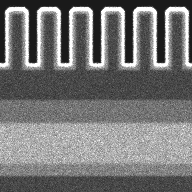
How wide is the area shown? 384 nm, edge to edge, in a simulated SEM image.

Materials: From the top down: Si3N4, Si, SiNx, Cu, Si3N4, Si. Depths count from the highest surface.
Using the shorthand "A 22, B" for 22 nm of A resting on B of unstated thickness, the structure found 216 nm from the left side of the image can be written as Si3N4 12, Si 172, SiNx 46, Cu 82, Si3N4 24, Si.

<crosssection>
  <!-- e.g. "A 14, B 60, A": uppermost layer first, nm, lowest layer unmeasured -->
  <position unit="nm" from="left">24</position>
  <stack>Si3N4 12, Si 172, SiNx 46, Cu 82, Si3N4 24, Si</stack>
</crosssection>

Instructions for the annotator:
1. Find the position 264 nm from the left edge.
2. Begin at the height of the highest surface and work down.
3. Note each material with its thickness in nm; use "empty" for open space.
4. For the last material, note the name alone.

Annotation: empty 112, Si3N4 12, Si 60, SiNx 46, Cu 82, Si3N4 24, Si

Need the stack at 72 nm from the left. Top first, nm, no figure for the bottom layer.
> empty 112, Si3N4 12, Si 60, SiNx 46, Cu 82, Si3N4 24, Si